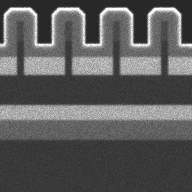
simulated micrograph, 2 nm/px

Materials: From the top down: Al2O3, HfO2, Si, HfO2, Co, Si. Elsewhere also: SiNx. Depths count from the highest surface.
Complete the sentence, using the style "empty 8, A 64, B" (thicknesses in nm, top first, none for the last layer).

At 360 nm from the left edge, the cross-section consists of empty 12, Al2O3 86, HfO2 36, Si 60, HfO2 30, Co 40, Si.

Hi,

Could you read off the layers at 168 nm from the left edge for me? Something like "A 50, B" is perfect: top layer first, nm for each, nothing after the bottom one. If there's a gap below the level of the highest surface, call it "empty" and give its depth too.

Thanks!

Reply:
empty 12, Al2O3 86, HfO2 36, Si 60, HfO2 30, Co 40, Si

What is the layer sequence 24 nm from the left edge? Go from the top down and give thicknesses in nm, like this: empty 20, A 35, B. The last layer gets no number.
Al2O3 98, HfO2 36, Si 60, HfO2 30, Co 40, Si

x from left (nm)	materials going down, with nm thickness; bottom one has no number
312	Al2O3 98, HfO2 36, Si 60, HfO2 30, Co 40, Si